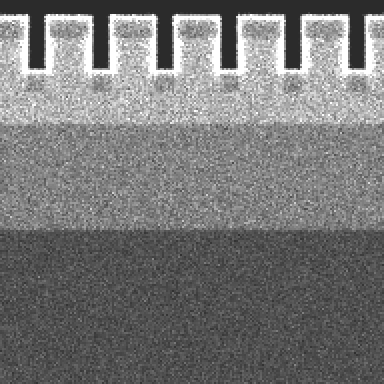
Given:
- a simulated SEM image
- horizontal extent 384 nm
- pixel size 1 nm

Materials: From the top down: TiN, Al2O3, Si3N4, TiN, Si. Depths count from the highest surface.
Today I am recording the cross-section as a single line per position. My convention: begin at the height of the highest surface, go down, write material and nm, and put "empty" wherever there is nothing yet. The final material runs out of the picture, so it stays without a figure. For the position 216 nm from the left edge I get TiN 22, Al2O3 86, Si3N4 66, TiN 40, Si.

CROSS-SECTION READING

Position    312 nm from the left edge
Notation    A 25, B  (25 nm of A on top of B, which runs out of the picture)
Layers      TiN 22, Al2O3 86, Si3N4 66, TiN 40, Si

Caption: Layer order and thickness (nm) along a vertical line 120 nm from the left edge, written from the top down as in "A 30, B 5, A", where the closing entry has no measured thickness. TiN 22, Al2O3 86, Si3N4 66, TiN 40, Si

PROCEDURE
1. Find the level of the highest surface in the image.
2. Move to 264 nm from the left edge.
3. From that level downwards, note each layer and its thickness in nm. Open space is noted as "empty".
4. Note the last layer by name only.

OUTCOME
TiN 22, Al2O3 86, Si3N4 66, TiN 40, Si